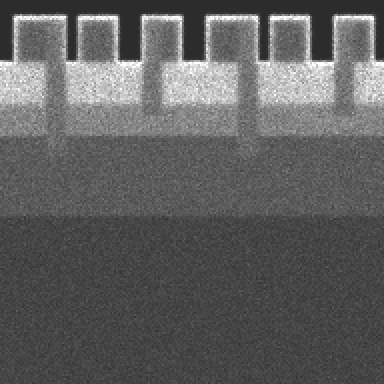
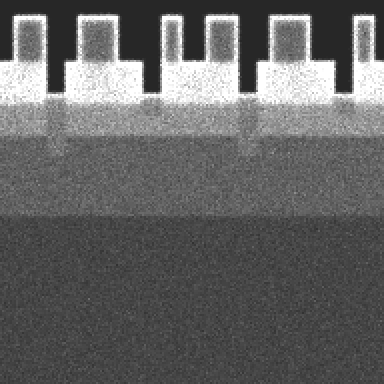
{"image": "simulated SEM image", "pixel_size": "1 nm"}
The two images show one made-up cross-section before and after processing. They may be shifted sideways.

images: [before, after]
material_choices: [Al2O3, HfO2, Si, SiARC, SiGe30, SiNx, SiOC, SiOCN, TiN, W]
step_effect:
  removed: TiN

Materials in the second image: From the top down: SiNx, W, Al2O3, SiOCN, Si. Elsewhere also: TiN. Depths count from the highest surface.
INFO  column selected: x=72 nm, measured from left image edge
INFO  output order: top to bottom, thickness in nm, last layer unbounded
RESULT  empty 46, W 42, Al2O3 32, SiOCN 80, Si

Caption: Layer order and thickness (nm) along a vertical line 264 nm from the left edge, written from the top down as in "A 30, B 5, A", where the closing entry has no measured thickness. empty 46, W 42, Al2O3 32, SiOCN 80, Si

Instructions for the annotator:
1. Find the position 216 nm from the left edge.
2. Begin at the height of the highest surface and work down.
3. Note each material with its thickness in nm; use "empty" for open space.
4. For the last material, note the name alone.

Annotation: SiNx 46, W 42, Al2O3 32, SiOCN 80, Si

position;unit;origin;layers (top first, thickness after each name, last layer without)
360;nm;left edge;SiNx 46, W 42, Al2O3 32, SiOCN 80, Si